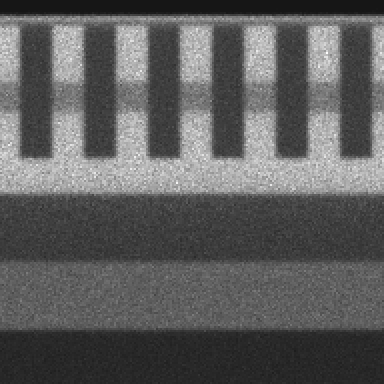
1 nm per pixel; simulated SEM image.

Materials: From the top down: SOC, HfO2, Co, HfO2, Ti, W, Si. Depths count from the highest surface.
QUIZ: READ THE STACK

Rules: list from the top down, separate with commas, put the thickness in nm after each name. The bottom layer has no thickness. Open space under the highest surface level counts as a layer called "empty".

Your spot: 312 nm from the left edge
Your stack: SOC 10, HfO2 56, Co 30, HfO2 82, Ti 68, W 68, Si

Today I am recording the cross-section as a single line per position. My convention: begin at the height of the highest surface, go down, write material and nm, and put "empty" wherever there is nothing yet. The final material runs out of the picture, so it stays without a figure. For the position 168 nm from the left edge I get SOC 142, HfO2 36, Ti 68, W 68, Si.